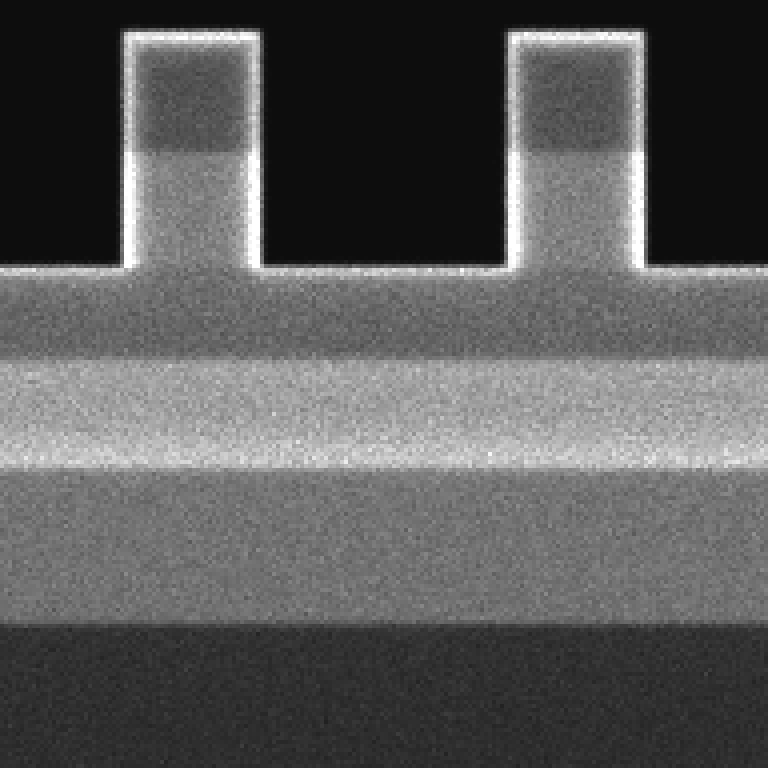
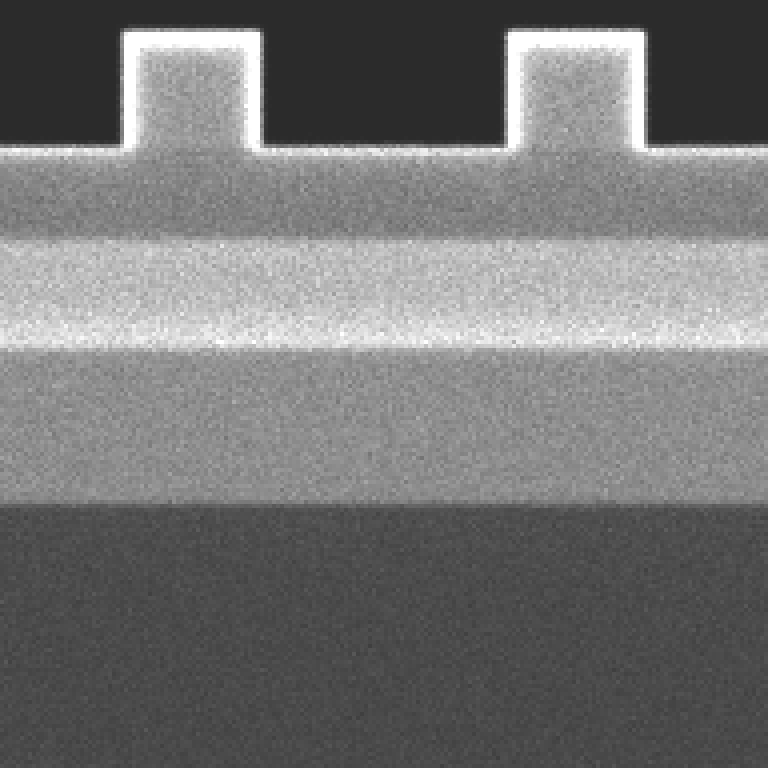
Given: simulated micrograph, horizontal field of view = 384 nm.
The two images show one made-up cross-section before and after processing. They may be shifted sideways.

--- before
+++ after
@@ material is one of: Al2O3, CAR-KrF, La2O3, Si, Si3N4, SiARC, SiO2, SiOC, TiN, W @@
SiARC removed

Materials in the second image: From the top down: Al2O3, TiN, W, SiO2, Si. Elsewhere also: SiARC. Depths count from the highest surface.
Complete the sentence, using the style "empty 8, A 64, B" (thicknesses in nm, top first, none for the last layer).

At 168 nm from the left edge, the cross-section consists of empty 58, TiN 46, W 54, SiO2 78, Si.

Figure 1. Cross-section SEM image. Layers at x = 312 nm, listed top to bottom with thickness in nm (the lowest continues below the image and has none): Al2O3 58, TiN 46, W 54, SiO2 78, Si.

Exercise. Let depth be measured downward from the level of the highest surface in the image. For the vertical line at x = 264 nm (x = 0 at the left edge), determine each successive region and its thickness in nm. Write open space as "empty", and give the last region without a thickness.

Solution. Al2O3 58, TiN 46, W 54, SiO2 78, Si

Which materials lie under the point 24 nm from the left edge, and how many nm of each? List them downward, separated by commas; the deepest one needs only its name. empty 58, TiN 46, W 54, SiO2 78, Si